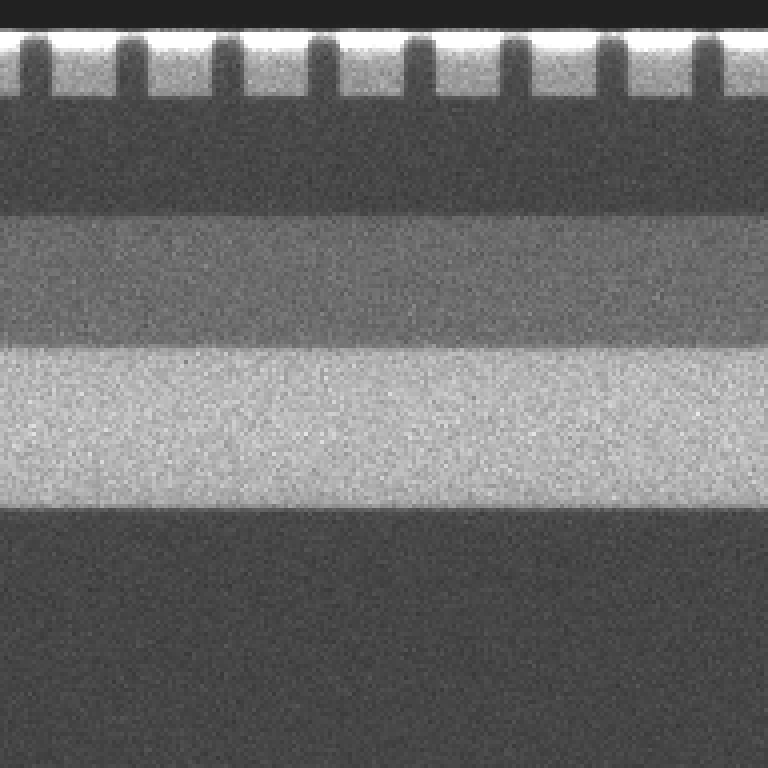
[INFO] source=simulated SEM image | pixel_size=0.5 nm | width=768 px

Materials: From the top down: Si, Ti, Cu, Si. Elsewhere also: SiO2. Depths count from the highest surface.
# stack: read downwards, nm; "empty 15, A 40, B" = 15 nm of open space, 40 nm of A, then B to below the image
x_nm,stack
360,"Si 92, Ti 66, Cu 80, Si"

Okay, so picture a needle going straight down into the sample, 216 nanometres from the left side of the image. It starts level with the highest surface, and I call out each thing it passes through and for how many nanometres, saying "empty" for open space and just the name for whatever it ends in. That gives Si 92, Ti 66, Cu 80, Si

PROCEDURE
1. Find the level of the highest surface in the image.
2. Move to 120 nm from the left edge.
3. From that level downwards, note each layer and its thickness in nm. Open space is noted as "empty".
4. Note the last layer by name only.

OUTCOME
Si 92, Ti 66, Cu 80, Si